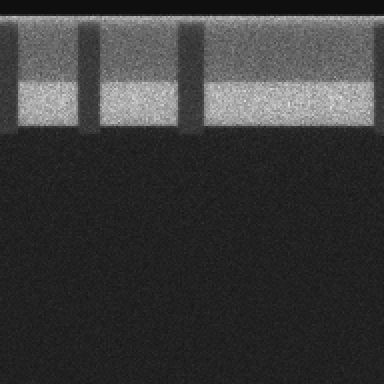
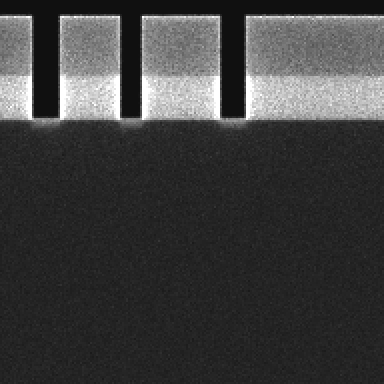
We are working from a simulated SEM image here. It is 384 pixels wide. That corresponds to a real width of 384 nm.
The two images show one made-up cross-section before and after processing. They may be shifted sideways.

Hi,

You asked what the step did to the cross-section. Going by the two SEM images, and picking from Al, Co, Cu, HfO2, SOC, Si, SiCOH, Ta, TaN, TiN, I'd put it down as SOC, removed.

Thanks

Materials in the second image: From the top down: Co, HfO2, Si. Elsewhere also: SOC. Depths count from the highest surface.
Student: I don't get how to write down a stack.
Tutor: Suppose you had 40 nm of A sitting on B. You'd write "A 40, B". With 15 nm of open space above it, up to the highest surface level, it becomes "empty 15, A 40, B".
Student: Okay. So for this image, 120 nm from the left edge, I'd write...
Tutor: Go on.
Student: empty 102, SOC 10, Si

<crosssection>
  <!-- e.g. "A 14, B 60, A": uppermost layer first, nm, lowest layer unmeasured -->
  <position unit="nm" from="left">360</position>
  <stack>Co 60, HfO2 44, Si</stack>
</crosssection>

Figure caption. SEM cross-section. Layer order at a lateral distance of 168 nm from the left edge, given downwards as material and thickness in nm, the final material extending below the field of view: Co 60, HfO2 44, Si